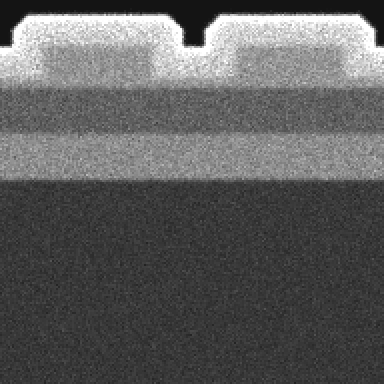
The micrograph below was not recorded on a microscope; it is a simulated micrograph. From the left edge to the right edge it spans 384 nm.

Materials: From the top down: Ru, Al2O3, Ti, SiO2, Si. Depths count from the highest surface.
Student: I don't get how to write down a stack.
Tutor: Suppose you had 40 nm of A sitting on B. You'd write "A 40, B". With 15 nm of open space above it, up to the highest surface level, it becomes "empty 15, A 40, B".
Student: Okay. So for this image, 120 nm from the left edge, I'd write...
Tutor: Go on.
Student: Ru 30, Al2O3 42, Ti 46, SiO2 46, Si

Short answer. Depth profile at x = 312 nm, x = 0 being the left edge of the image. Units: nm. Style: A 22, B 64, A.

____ Ru 30, Al2O3 42, Ti 46, SiO2 46, Si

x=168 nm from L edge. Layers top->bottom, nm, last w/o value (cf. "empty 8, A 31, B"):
empty 2, Ru 60, Al2O3 10, Ti 46, SiO2 46, Si